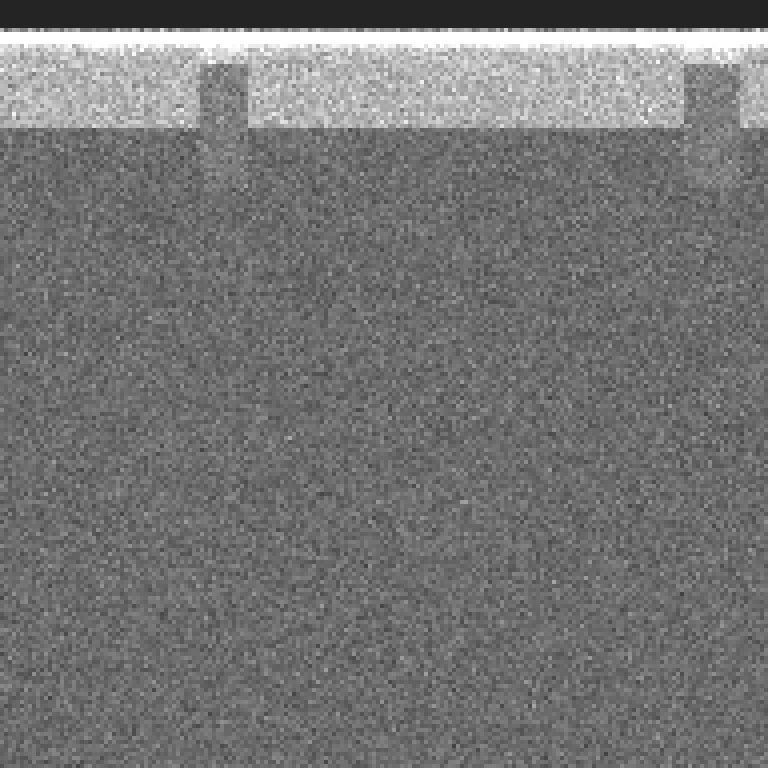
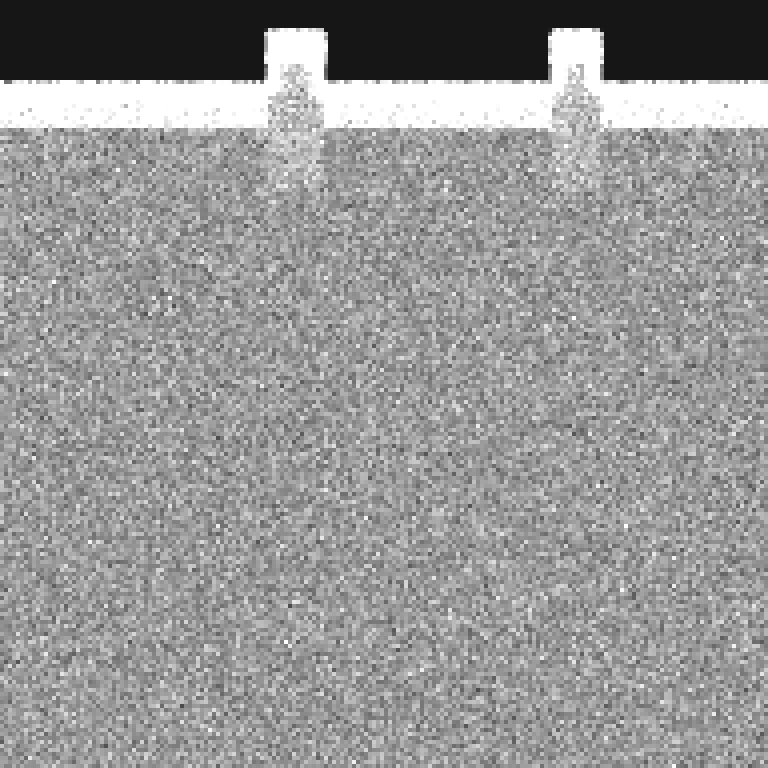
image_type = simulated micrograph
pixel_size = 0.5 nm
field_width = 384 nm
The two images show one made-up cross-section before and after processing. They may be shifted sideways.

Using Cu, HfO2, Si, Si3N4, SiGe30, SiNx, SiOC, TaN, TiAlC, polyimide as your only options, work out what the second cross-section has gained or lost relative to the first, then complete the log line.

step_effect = removed SiNx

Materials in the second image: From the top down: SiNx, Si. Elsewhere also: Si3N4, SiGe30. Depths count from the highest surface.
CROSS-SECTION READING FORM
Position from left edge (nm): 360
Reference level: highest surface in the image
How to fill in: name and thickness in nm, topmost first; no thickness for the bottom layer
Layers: empty 26, SiNx 22, Si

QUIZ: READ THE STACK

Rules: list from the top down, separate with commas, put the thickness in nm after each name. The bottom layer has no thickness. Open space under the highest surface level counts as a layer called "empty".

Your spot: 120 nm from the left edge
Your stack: empty 26, SiNx 22, Si